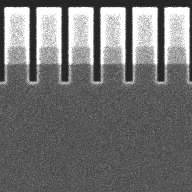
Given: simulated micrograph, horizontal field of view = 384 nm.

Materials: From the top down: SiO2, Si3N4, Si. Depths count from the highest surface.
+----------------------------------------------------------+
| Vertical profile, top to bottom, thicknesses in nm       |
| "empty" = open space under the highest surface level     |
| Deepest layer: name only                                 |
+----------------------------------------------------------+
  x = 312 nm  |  SiO2 78, Si3N4 34, Si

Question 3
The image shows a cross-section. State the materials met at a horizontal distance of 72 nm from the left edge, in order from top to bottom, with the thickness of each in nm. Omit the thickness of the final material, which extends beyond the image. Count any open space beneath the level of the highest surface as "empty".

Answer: empty 148, Si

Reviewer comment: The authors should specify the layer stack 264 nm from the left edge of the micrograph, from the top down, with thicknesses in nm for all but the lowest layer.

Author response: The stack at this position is empty 148, Si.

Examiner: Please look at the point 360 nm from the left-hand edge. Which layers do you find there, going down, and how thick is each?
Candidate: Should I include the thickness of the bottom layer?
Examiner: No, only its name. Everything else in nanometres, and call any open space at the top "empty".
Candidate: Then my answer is SiO2 78, Si3N4 34, Si